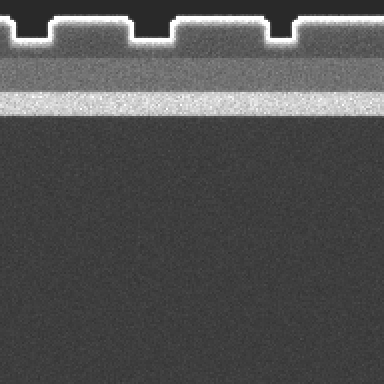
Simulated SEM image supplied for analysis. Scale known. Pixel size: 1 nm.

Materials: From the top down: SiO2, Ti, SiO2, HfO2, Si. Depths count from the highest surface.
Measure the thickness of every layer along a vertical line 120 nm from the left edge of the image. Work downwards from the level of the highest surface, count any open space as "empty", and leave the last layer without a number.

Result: SiO2 10, Ti 32, SiO2 34, HfO2 24, Si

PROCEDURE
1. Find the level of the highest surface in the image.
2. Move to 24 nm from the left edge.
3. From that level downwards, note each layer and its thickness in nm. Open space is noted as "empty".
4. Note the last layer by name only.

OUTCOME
empty 22, SiO2 10, Ti 10, SiO2 34, HfO2 24, Si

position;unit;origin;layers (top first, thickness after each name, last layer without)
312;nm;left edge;SiO2 10, Ti 32, SiO2 34, HfO2 24, Si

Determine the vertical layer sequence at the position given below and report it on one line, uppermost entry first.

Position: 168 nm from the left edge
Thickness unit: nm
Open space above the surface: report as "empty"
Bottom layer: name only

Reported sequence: empty 22, SiO2 10, Ti 10, SiO2 34, HfO2 24, Si